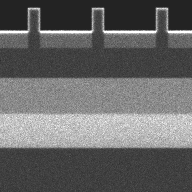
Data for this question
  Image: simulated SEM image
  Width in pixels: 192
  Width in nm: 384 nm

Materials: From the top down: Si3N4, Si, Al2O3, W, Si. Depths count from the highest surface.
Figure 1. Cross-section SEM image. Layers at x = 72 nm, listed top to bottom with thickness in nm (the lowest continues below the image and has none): Si 140, Al2O3 72, W 68, Si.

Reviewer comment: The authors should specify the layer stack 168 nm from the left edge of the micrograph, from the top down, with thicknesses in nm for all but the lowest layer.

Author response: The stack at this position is empty 46, Si3N4 34, Si 60, Al2O3 72, W 68, Si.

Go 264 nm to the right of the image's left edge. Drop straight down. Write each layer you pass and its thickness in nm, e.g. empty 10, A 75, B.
empty 46, Si3N4 34, Si 60, Al2O3 72, W 68, Si